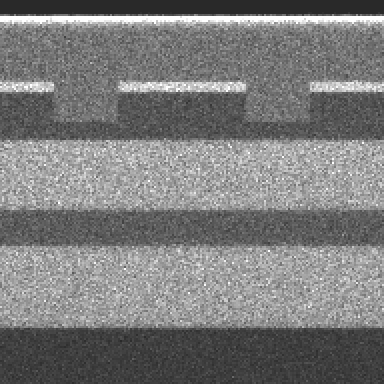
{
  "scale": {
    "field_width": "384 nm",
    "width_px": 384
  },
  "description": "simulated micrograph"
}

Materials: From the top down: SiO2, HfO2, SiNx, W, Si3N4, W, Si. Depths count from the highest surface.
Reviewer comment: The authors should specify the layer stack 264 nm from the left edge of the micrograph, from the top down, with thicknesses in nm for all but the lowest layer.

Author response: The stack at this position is SiO2 106, SiNx 18, W 70, Si3N4 36, W 82, Si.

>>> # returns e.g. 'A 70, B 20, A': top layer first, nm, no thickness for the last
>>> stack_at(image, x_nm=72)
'SiO2 106, SiNx 18, W 70, Si3N4 36, W 82, Si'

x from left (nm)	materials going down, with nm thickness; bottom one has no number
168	SiO2 66, HfO2 10, SiNx 48, W 70, Si3N4 36, W 82, Si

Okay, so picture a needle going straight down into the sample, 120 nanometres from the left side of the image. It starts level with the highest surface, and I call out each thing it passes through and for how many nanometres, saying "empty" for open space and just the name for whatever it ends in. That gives SiO2 66, HfO2 10, SiNx 48, W 70, Si3N4 36, W 82, Si